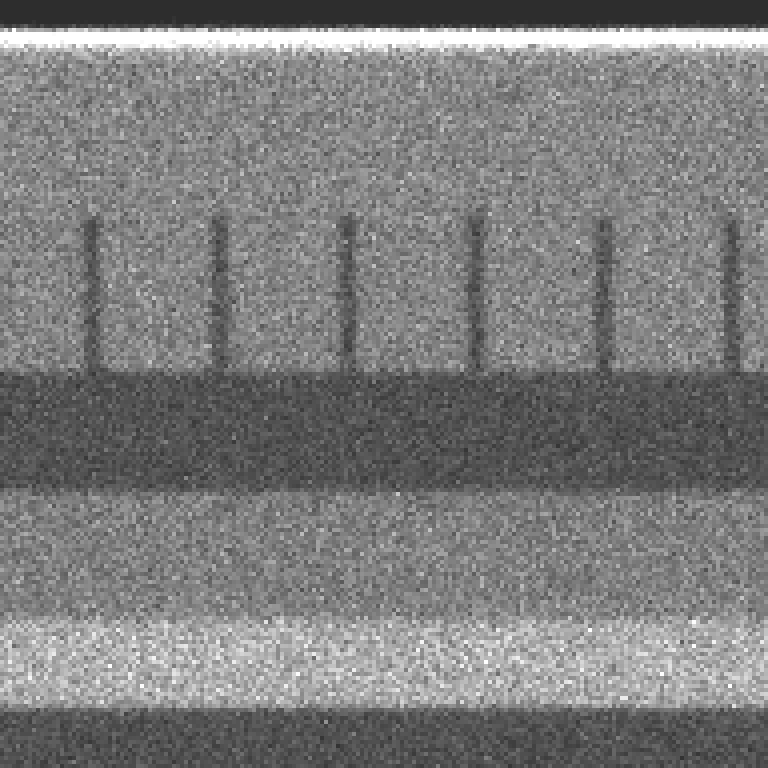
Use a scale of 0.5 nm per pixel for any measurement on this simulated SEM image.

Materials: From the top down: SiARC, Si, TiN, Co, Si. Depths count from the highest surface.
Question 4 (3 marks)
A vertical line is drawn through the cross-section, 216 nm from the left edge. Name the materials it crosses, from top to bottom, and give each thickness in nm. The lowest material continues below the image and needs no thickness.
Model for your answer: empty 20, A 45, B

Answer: SiARC 170, Si 60, TiN 64, Co 44, Si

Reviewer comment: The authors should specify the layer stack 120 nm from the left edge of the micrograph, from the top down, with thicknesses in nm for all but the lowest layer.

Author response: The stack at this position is SiARC 170, Si 60, TiN 64, Co 44, Si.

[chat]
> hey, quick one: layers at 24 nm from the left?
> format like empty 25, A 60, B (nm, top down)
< SiARC 170, Si 60, TiN 64, Co 44, Si